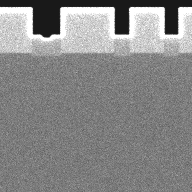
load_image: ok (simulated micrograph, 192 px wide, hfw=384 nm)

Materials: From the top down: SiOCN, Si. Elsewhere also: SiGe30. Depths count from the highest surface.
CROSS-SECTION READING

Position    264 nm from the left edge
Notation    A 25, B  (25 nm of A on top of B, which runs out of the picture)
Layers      SiOCN 90, Si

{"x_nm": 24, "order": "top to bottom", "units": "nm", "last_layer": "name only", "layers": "SiOCN 90, Si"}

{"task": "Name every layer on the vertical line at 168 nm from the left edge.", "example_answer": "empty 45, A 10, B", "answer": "SiOCN 90, Si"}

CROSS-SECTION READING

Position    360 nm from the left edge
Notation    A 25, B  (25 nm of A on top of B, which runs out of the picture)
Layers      SiOCN 90, Si